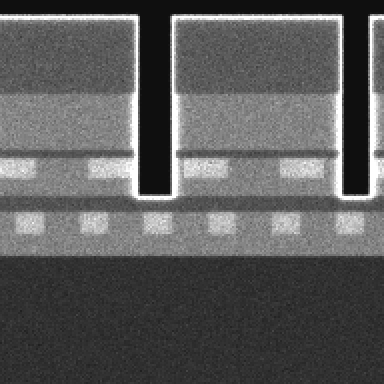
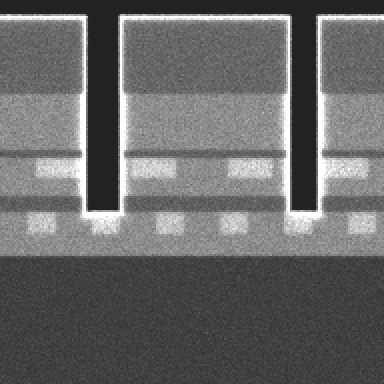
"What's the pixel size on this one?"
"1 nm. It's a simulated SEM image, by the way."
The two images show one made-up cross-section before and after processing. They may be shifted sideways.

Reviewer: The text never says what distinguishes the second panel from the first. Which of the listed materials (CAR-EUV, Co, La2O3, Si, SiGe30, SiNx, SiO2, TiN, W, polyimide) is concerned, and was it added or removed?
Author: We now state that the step removed SiNx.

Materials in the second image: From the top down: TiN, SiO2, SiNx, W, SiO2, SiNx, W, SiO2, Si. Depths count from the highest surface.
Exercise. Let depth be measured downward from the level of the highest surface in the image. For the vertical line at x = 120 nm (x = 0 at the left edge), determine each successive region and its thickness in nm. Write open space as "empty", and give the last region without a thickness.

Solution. TiN 78, SiO2 56, SiNx 8, SiO2 38, SiNx 16, SiO2 44, Si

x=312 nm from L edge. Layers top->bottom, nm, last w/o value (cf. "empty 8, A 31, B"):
empty 196, SiO2 44, Si